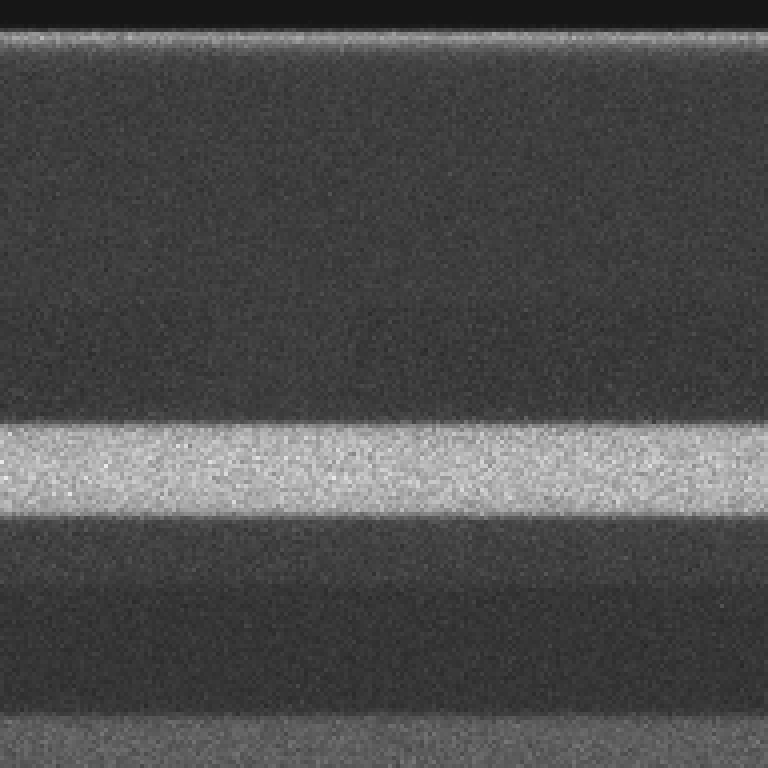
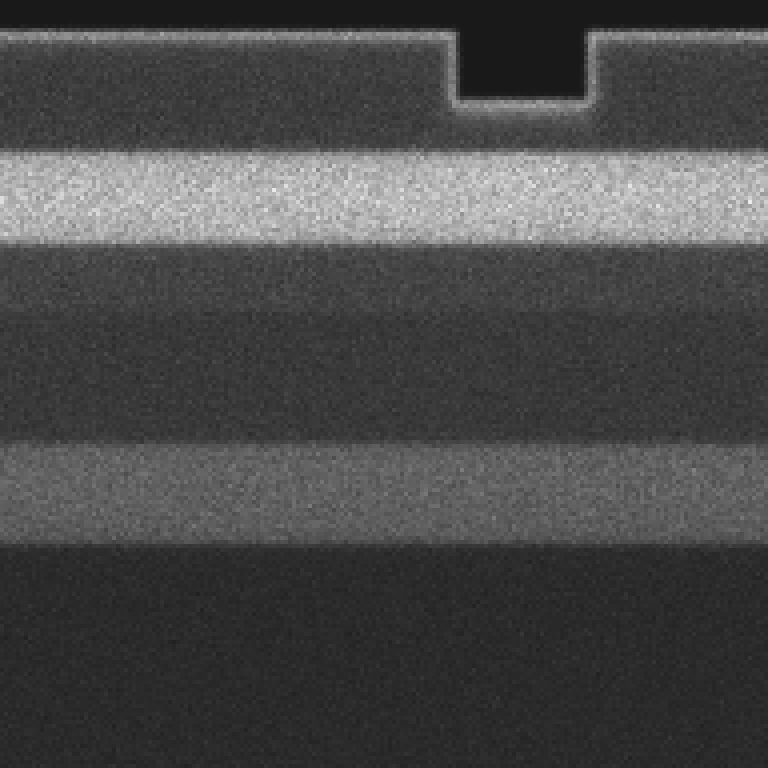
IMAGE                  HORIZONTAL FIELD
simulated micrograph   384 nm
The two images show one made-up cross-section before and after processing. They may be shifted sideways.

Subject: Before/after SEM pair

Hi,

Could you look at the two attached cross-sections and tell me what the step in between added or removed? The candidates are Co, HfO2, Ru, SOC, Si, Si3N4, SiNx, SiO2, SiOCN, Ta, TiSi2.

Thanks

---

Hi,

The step removed SOC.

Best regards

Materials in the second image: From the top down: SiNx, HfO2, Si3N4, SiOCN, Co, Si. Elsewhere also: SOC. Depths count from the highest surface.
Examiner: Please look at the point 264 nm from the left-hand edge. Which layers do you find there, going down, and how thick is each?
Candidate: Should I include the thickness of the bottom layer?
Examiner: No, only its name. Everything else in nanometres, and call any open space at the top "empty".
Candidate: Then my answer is empty 34, SOC 26, HfO2 46, Si3N4 34, SiOCN 66, Co 50, Si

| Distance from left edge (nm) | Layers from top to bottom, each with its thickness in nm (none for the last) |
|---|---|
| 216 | SiNx 60, HfO2 46, Si3N4 34, SiOCN 66, Co 50, Si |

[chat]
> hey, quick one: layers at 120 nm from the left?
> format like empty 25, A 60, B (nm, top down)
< SiNx 60, HfO2 46, Si3N4 34, SiOCN 66, Co 50, Si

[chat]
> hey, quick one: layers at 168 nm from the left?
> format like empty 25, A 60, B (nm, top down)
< SiNx 60, HfO2 46, Si3N4 34, SiOCN 66, Co 50, Si